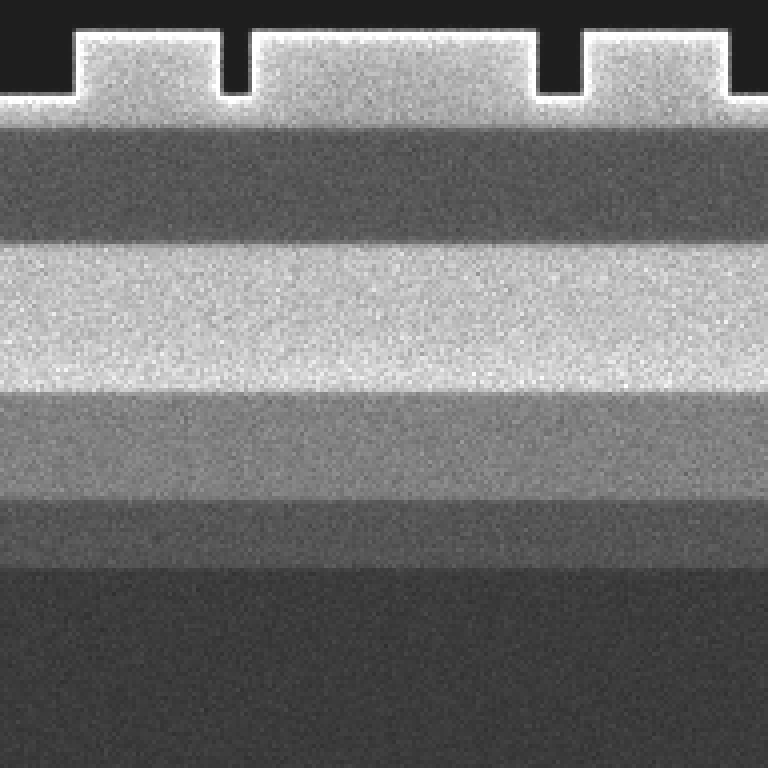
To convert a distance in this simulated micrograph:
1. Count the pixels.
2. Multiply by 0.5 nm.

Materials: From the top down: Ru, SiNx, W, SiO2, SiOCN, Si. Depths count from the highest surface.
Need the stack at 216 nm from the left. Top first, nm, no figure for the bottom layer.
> Ru 48, SiNx 58, W 74, SiO2 54, SiOCN 34, Si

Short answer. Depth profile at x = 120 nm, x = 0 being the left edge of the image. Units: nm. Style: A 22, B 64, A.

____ empty 32, Ru 16, SiNx 58, W 74, SiO2 54, SiOCN 34, Si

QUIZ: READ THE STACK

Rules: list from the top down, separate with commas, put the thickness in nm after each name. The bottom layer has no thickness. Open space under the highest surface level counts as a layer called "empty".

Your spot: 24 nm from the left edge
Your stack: empty 32, Ru 16, SiNx 58, W 74, SiO2 54, SiOCN 34, Si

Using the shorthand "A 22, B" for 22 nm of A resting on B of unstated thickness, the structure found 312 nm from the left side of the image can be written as Ru 48, SiNx 58, W 74, SiO2 54, SiOCN 34, Si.